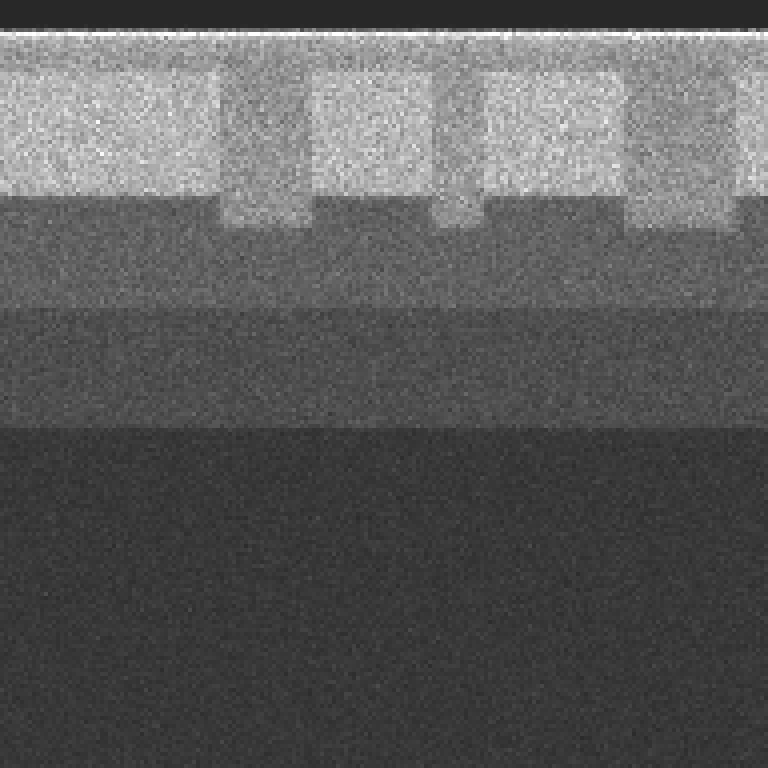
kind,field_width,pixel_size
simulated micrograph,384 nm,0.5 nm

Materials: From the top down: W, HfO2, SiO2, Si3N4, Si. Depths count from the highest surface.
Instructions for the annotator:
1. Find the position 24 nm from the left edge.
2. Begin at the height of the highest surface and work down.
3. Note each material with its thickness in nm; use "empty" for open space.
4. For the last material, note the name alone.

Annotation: W 20, HfO2 62, SiO2 56, Si3N4 60, Si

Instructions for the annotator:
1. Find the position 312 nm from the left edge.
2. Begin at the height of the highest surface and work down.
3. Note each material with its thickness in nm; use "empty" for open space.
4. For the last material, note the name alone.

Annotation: W 98, SiO2 40, Si3N4 60, Si